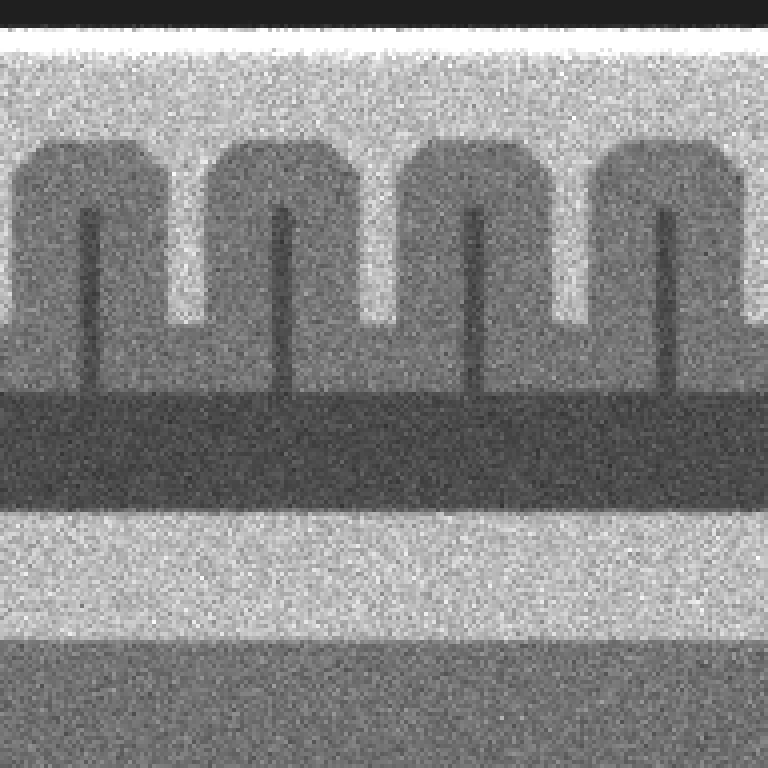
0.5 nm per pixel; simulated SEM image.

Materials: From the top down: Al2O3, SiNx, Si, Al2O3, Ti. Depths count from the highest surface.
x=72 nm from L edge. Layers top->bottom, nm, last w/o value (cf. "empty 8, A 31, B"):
Al2O3 60, SiNx 120, Si 60, Al2O3 64, Ti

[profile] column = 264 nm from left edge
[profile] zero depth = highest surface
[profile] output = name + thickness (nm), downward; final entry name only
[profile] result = Al2O3 60, SiNx 120, Si 60, Al2O3 64, Ti